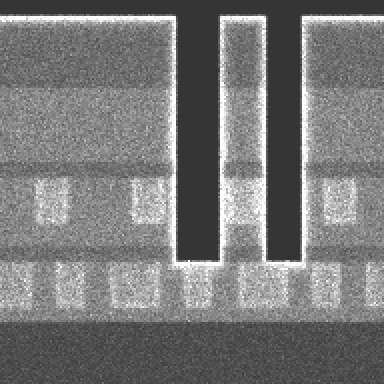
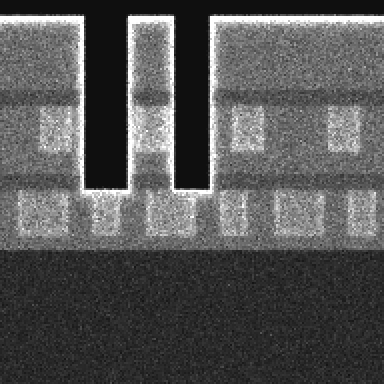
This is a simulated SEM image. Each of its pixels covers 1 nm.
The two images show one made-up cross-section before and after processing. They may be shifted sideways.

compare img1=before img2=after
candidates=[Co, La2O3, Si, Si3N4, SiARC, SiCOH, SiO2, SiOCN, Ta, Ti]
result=removed:SiARC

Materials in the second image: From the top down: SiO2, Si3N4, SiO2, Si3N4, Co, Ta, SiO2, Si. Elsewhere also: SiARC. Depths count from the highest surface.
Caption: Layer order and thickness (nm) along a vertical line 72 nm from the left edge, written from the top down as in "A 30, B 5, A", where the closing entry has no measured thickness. SiO2 74, Si3N4 16, SiO2 68, Si3N4 16, SiO2 60, Si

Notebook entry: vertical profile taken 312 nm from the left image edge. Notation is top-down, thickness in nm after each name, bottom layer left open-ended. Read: SiO2 74, Si3N4 16, SiO2 68, Si3N4 16, Co 40, Ta 6, SiO2 14, Si